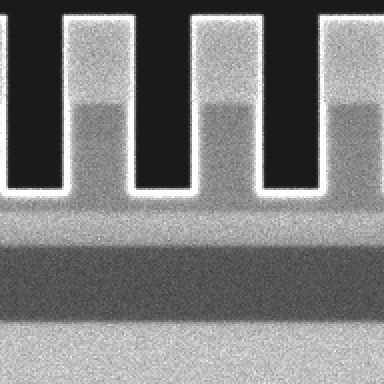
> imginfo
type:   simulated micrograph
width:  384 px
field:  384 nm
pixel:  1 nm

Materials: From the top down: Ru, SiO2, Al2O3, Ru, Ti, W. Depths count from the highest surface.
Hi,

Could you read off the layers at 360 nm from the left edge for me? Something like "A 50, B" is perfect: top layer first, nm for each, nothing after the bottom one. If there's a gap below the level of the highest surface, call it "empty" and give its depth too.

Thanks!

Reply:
Ru 88, SiO2 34, Al2O3 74, Ru 34, Ti 76, W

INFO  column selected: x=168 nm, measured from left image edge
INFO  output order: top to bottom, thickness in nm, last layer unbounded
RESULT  empty 174, Al2O3 22, Ru 34, Ti 76, W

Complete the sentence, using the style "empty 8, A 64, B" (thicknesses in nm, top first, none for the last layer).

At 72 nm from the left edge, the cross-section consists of Ru 88, SiO2 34, Al2O3 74, Ru 34, Ti 76, W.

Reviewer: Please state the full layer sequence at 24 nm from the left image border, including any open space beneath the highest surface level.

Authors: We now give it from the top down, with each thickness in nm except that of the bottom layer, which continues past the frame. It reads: empty 174, Al2O3 22, Ru 34, Ti 76, W